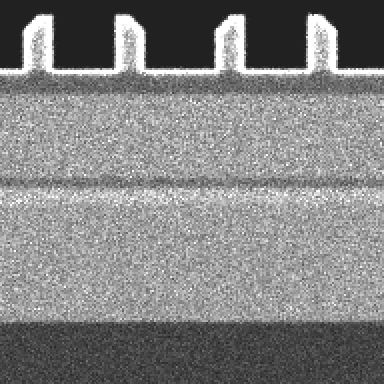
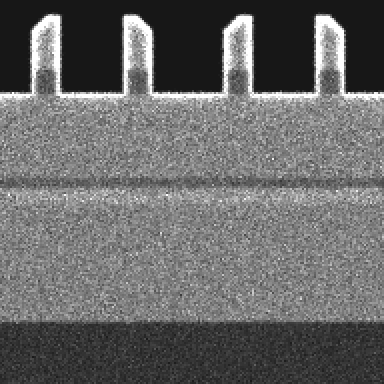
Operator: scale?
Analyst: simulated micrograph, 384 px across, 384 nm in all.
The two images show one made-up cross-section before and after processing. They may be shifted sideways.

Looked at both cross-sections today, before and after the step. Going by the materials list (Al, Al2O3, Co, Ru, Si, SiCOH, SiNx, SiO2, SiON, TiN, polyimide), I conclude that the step removed SiNx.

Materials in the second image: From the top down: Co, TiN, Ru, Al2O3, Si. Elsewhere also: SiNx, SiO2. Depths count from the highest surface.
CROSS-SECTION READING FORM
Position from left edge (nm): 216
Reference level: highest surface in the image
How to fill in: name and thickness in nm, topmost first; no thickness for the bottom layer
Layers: empty 78, Co 84, TiN 10, Ru 16, Al2O3 118, Si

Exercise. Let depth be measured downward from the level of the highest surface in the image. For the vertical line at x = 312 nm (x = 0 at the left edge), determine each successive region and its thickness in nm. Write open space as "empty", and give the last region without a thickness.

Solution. empty 78, Co 84, TiN 10, Ru 16, Al2O3 118, Si